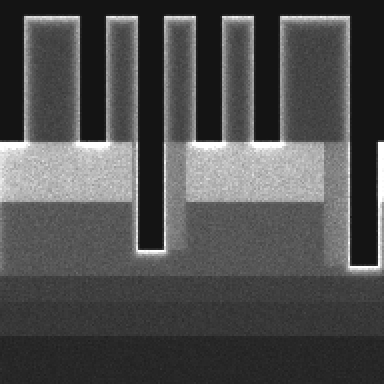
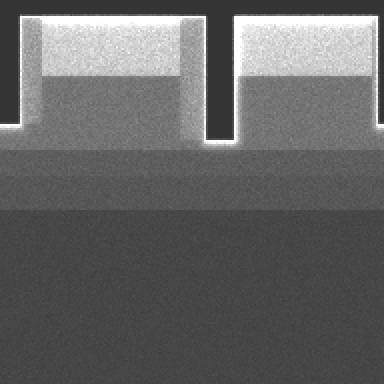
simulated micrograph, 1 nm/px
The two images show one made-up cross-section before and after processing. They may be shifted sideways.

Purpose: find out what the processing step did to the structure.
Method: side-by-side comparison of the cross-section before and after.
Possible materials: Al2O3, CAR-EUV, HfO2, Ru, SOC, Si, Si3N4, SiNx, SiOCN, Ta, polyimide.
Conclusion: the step removed SOC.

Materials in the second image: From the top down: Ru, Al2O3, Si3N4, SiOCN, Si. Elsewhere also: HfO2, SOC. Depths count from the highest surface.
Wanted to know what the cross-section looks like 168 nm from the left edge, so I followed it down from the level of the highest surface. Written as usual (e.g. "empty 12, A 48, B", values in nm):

HfO2 60, Al2O3 74, Si3N4 26, SiOCN 34, Si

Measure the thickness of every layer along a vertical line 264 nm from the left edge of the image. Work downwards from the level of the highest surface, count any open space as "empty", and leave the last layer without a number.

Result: HfO2 60, Al2O3 74, Si3N4 26, SiOCN 34, Si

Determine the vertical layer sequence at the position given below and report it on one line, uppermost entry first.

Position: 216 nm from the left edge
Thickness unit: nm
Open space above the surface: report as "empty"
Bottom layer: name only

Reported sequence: empty 124, Al2O3 10, Si3N4 26, SiOCN 34, Si